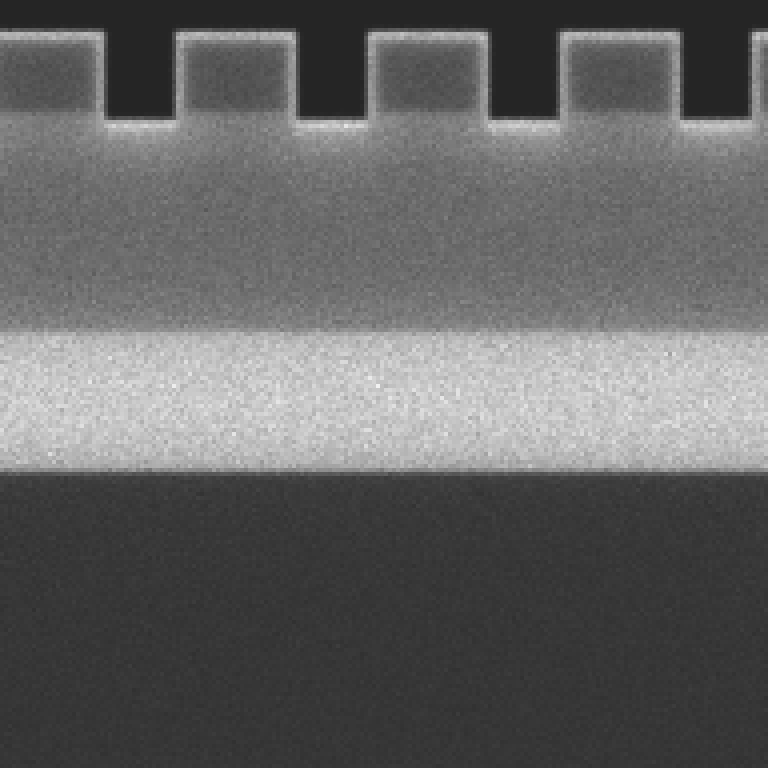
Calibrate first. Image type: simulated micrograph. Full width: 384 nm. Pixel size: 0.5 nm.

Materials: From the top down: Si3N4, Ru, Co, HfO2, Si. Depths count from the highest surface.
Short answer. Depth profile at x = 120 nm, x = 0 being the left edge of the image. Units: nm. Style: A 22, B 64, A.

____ Si3N4 40, Ru 24, Co 86, HfO2 70, Si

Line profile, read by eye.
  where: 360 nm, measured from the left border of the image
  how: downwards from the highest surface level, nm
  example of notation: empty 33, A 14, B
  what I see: empty 44, Ru 20, Co 86, HfO2 70, Si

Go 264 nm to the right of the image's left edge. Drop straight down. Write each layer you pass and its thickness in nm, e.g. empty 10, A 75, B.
empty 44, Ru 20, Co 86, HfO2 70, Si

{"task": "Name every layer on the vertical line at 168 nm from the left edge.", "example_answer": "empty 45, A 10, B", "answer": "empty 44, Ru 20, Co 86, HfO2 70, Si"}